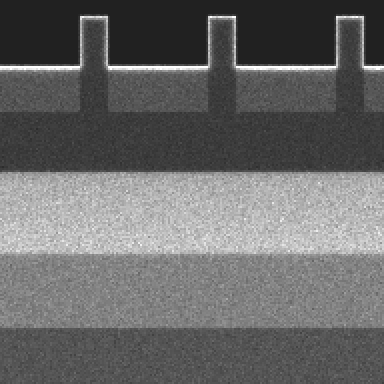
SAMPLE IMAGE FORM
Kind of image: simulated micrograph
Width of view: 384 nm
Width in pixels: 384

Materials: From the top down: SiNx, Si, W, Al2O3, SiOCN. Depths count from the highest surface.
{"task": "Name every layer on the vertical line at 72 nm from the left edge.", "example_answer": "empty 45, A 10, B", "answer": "empty 50, SiNx 46, Si 60, W 82, Al2O3 74, SiOCN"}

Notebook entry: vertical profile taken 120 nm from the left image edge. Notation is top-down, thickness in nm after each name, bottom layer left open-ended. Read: empty 50, SiNx 46, Si 60, W 82, Al2O3 74, SiOCN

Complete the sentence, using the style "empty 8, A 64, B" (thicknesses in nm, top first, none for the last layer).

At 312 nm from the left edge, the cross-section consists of empty 50, SiNx 46, Si 60, W 82, Al2O3 74, SiOCN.